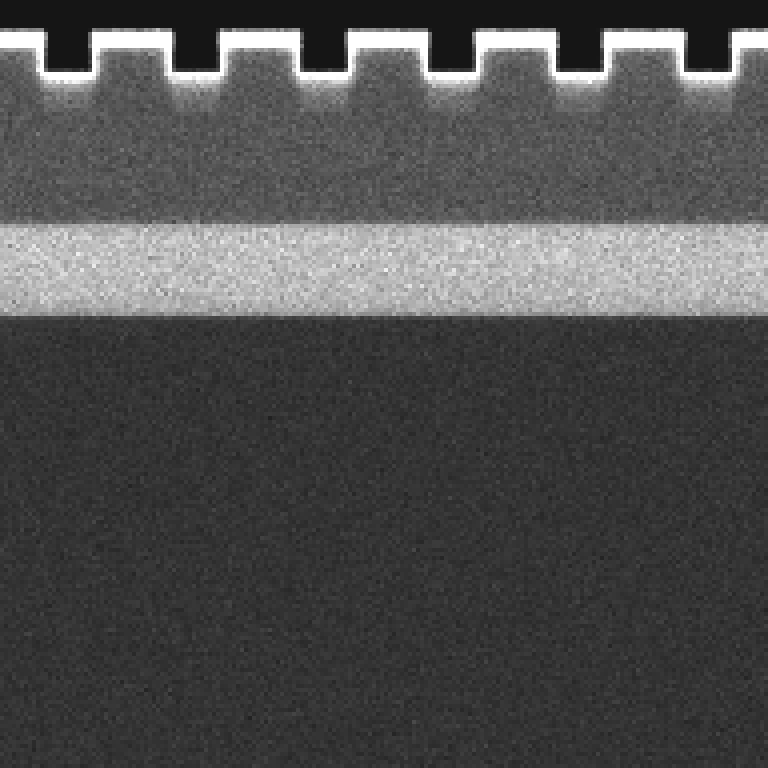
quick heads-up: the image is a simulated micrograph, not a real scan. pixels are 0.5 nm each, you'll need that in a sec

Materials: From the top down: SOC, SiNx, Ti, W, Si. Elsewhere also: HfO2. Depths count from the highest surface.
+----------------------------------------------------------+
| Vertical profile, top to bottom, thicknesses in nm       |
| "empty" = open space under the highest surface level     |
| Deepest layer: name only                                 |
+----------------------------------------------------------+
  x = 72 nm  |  HfO2 8, SiNx 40, Ti 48, W 46, Si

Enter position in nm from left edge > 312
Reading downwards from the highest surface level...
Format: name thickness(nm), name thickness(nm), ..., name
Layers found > HfO2 8, SiNx 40, Ti 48, W 46, Si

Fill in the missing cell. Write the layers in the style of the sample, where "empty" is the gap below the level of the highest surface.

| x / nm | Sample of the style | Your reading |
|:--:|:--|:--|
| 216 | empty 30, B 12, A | empty 20, SOC 20, SiNx 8, Ti 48, W 46, Si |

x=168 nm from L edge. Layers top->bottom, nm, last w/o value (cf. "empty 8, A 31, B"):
empty 20, SOC 20, SiNx 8, Ti 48, W 46, Si